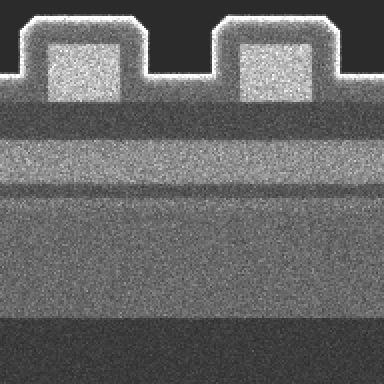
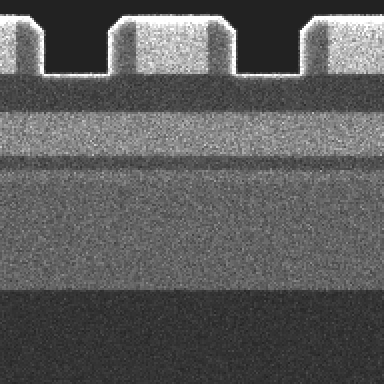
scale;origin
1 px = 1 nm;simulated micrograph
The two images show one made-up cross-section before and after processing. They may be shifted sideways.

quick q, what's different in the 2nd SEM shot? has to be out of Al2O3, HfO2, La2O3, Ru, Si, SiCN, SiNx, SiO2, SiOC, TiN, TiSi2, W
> SiO2 removed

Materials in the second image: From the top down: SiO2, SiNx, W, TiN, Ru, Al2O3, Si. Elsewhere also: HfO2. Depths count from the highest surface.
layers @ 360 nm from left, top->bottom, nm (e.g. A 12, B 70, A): HfO2 58, SiNx 38, W 44, TiN 14, Ru 12, Al2O3 108, Si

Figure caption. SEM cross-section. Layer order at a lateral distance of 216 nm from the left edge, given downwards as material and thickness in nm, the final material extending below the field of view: SiO2 58, SiNx 38, W 44, TiN 14, Ru 12, Al2O3 108, Si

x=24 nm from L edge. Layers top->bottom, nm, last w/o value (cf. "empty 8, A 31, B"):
SiO2 58, SiNx 38, W 44, TiN 14, Ru 12, Al2O3 108, Si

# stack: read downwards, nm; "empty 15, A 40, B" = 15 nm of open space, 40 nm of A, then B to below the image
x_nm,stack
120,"empty 2, SiO2 56, SiNx 38, W 44, TiN 14, Ru 12, Al2O3 108, Si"